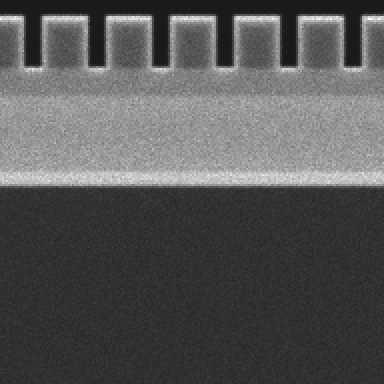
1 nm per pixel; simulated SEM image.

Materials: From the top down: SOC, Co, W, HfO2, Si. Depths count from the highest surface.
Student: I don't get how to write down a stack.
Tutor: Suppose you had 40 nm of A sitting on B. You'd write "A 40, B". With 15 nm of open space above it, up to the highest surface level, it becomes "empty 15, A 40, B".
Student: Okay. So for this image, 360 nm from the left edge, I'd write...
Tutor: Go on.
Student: empty 52, Co 28, W 76, HfO2 14, Si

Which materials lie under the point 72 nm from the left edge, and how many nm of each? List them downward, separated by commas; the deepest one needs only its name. SOC 52, Co 28, W 76, HfO2 14, Si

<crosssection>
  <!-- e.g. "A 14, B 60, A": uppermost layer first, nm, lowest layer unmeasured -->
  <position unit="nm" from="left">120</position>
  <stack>SOC 52, Co 28, W 76, HfO2 14, Si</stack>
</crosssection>